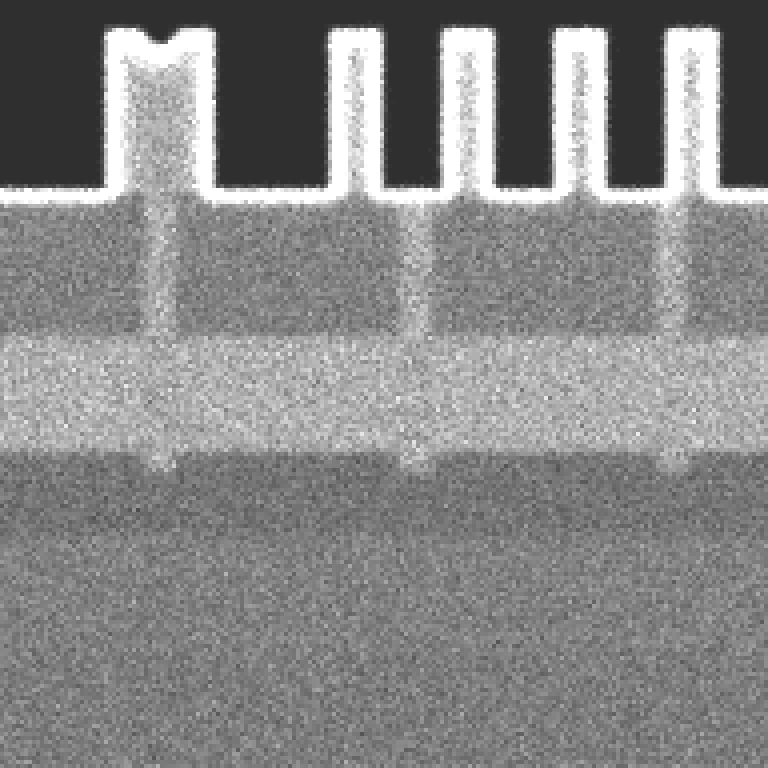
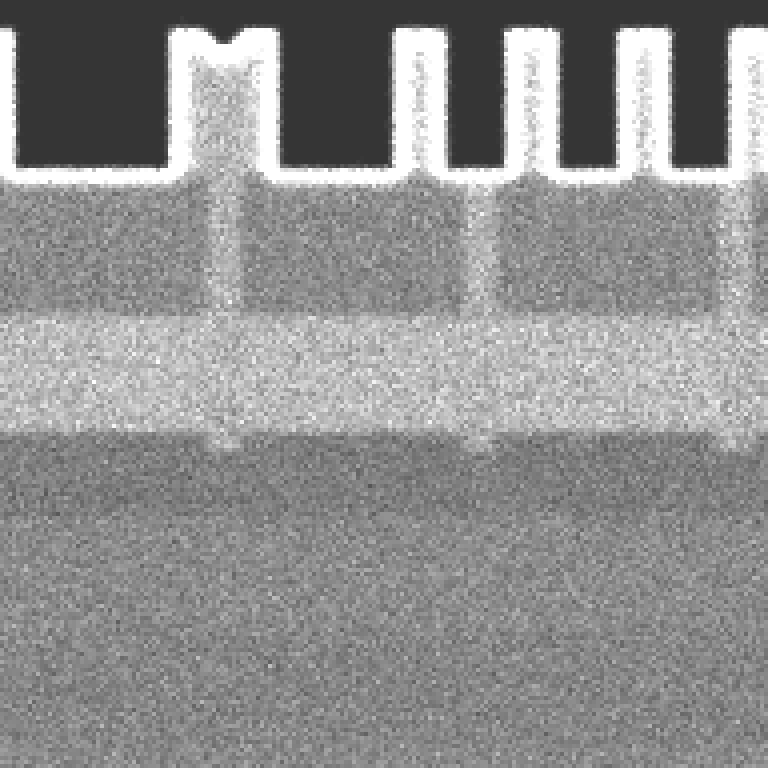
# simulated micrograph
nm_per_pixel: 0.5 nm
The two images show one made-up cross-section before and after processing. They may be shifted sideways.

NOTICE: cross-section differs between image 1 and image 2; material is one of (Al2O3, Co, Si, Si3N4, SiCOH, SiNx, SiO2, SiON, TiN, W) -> removed: SiO2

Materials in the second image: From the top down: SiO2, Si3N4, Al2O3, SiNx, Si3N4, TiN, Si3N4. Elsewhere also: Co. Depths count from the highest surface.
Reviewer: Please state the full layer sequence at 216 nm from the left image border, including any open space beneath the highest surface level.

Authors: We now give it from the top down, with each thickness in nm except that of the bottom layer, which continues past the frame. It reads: SiO2 70, Si3N4 72, Al2O3 58, SiNx 42, Si3N4 58, TiN 56, Si3N4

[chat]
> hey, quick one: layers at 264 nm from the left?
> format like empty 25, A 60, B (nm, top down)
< SiO2 70, Si3N4 72, Al2O3 58, SiNx 42, Si3N4 58, TiN 56, Si3N4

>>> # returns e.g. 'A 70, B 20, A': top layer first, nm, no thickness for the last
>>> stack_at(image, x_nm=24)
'empty 70, Si3N4 72, Al2O3 58, SiNx 42, Si3N4 58, TiN 56, Si3N4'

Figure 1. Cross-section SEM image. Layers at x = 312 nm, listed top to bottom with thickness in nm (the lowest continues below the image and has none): SiO2 70, Si3N4 72, Al2O3 58, SiNx 42, Si3N4 58, TiN 56, Si3N4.